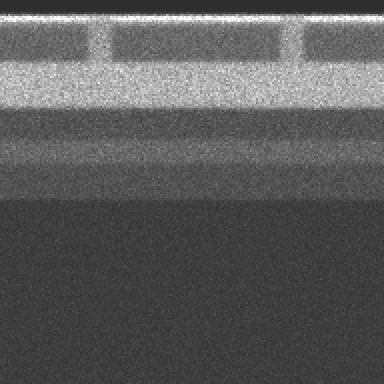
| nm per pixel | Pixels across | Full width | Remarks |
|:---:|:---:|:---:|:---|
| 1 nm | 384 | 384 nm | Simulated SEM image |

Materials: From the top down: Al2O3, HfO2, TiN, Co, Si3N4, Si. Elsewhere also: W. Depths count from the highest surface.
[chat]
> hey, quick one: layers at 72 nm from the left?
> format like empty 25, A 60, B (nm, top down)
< Al2O3 46, HfO2 46, TiN 32, Co 24, Si3N4 36, Si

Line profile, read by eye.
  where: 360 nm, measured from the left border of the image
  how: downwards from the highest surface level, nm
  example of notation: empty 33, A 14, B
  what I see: Al2O3 46, HfO2 46, TiN 32, Co 24, Si3N4 36, Si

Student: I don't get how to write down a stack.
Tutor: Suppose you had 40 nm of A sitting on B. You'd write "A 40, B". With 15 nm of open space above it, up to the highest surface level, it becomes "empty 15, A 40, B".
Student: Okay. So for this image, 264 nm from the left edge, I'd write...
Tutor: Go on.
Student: Al2O3 46, HfO2 46, TiN 32, Co 24, Si3N4 36, Si